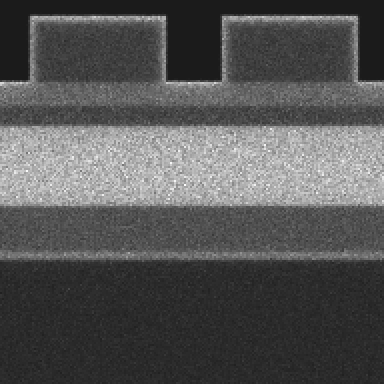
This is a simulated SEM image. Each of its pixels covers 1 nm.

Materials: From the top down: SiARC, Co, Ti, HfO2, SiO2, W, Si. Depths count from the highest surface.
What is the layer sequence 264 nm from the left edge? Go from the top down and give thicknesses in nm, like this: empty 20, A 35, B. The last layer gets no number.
SiARC 66, Co 24, Ti 20, HfO2 80, SiO2 46, W 8, Si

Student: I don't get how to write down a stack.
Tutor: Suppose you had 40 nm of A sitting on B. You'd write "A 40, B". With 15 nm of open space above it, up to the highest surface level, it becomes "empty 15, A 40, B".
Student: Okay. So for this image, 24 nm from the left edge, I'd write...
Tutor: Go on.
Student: empty 66, Co 24, Ti 20, HfO2 80, SiO2 46, W 8, Si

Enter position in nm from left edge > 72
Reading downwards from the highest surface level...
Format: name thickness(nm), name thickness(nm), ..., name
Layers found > SiARC 66, Co 24, Ti 20, HfO2 80, SiO2 46, W 8, Si